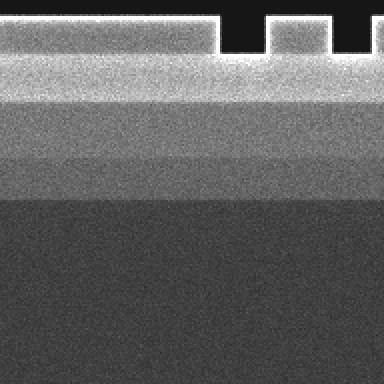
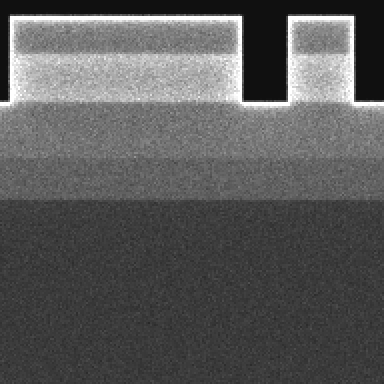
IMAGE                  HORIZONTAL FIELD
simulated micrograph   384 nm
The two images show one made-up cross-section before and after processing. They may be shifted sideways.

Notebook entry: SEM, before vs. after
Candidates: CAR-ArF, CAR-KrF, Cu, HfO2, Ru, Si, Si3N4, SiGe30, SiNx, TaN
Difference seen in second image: Ru removed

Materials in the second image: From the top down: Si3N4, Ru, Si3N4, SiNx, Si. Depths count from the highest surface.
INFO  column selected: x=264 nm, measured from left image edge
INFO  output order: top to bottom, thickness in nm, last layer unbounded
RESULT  empty 86, Si3N4 56, SiNx 42, Si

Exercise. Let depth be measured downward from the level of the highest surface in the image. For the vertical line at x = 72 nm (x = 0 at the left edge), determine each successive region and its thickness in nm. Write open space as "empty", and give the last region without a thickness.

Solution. Si3N4 38, Ru 48, Si3N4 56, SiNx 42, Si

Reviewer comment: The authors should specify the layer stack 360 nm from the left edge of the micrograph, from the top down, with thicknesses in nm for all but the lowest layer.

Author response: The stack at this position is empty 86, Si3N4 56, SiNx 42, Si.